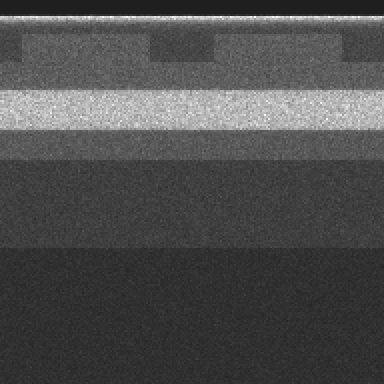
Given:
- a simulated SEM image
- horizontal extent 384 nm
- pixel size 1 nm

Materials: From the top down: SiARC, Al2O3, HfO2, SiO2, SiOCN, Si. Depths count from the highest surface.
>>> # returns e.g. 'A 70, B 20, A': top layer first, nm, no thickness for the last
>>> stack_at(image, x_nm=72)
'SiARC 18, Al2O3 56, HfO2 40, SiO2 30, SiOCN 88, Si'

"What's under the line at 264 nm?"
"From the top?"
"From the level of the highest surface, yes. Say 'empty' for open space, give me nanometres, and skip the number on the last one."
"SiARC 18, Al2O3 56, HfO2 40, SiO2 30, SiOCN 88, Si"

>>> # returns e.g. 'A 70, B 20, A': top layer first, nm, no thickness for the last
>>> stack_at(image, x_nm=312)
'SiARC 18, Al2O3 56, HfO2 40, SiO2 30, SiOCN 88, Si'